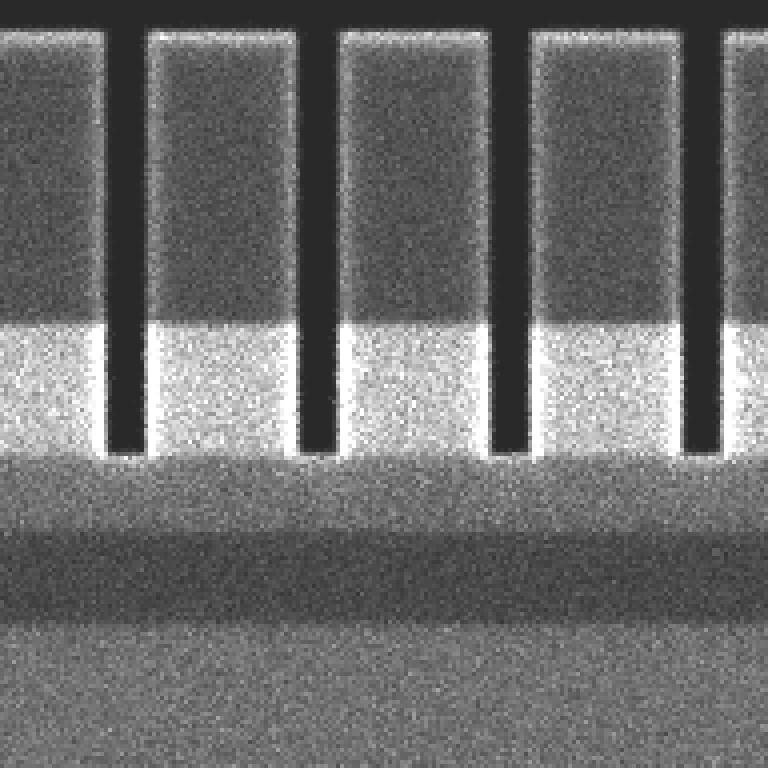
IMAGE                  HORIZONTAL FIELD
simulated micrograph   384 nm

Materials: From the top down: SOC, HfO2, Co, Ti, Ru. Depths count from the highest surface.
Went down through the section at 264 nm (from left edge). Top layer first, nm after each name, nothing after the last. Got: empty 212, Co 38, Ti 46, Ru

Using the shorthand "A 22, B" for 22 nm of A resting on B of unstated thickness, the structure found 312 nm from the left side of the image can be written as SOC 146, HfO2 66, Co 38, Ti 46, Ru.